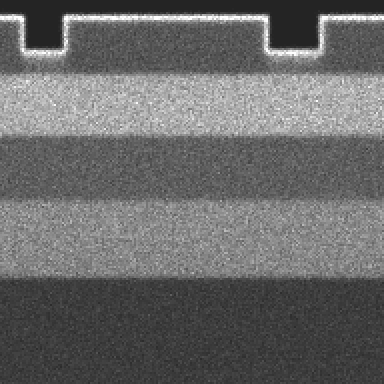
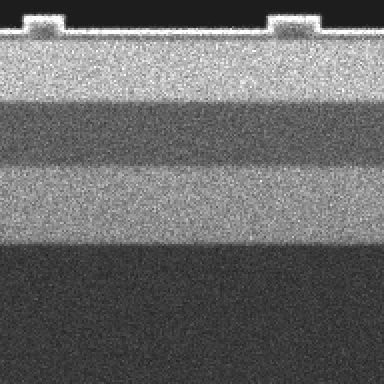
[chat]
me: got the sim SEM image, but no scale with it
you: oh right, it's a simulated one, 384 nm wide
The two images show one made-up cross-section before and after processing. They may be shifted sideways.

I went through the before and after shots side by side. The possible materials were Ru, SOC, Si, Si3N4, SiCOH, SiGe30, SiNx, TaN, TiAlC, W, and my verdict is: removed, SiNx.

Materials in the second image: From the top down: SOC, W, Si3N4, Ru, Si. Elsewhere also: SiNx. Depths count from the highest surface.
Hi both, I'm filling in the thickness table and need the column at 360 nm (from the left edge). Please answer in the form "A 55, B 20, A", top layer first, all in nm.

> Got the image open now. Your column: empty 14, SiNx 10, W 62, Si3N4 64, Ru 78, Si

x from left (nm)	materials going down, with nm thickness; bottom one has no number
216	empty 14, SiNx 10, W 62, Si3N4 64, Ru 78, Si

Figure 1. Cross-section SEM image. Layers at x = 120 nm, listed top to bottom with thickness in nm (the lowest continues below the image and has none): empty 14, SiNx 10, W 62, Si3N4 64, Ru 78, Si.